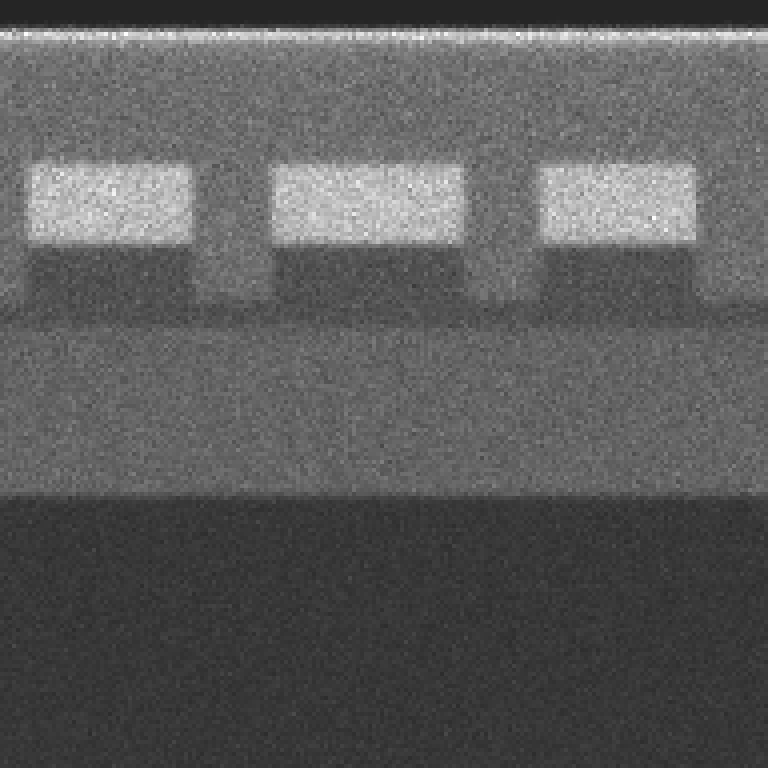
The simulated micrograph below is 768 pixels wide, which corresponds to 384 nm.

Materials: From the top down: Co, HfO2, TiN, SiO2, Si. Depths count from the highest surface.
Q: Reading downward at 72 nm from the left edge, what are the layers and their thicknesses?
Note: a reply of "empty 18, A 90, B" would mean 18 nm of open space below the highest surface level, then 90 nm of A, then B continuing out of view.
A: Co 66, HfO2 40, TiN 42, SiO2 84, Si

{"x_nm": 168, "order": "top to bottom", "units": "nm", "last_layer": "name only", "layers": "Co 66, HfO2 40, TiN 42, SiO2 84, Si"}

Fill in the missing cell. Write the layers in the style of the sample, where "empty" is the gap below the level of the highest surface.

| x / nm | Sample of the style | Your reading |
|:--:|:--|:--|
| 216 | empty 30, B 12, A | Co 66, HfO2 40, TiN 42, SiO2 84, Si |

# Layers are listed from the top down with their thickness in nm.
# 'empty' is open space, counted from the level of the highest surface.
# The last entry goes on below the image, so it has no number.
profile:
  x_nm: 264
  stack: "Co 134, TiN 14, SiO2 84, Si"